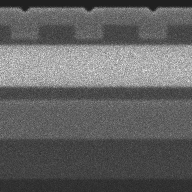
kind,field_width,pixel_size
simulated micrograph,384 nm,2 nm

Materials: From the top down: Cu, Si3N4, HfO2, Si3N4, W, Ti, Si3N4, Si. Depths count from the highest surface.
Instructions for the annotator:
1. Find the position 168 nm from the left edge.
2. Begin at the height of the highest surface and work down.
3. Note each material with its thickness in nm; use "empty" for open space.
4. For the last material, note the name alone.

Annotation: empty 2, Cu 60, Si3N4 12, HfO2 84, Si3N4 26, W 78, Ti 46, Si3N4 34, Si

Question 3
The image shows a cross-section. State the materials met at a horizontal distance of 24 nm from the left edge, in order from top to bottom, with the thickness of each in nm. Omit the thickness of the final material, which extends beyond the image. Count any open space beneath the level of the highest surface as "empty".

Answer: Cu 62, Si3N4 12, HfO2 84, Si3N4 26, W 78, Ti 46, Si3N4 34, Si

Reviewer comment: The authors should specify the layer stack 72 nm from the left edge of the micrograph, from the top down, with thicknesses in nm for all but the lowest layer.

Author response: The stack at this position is Cu 62, Si3N4 12, HfO2 84, Si3N4 26, W 78, Ti 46, Si3N4 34, Si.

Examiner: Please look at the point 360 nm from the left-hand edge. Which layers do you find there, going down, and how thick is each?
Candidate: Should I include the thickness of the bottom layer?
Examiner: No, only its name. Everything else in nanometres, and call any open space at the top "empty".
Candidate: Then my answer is Cu 34, Si3N4 40, HfO2 84, Si3N4 26, W 78, Ti 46, Si3N4 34, Si